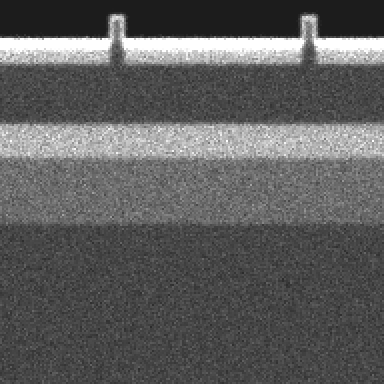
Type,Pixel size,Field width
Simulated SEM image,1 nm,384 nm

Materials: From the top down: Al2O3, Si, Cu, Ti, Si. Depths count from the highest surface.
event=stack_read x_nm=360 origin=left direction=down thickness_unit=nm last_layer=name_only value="empty 24, Al2O3 24, Si 60, Cu 34, Ti 66, Si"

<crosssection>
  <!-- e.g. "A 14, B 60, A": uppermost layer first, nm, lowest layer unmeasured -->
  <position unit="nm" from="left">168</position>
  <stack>empty 24, Al2O3 24, Si 60, Cu 34, Ti 66, Si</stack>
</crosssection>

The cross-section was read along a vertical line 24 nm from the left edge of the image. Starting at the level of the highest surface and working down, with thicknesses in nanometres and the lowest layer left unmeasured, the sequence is empty 24, Al2O3 24, Si 60, Cu 34, Ti 66, Si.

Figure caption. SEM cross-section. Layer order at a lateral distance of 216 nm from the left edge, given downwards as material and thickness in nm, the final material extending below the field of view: empty 24, Al2O3 24, Si 60, Cu 34, Ti 66, Si